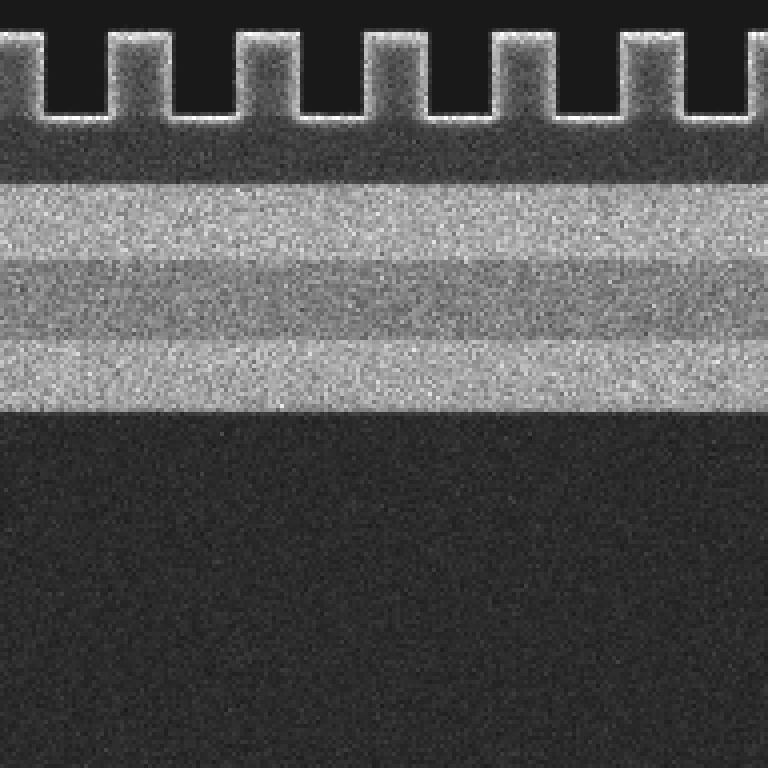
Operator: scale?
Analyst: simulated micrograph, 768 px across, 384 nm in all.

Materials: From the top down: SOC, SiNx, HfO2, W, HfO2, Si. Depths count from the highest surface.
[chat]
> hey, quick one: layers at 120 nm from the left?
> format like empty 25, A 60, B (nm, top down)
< SOC 42, SiNx 34, HfO2 38, W 40, HfO2 36, Si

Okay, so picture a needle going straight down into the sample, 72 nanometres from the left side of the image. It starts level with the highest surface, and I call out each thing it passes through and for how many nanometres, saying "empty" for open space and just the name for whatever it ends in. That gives SOC 42, SiNx 34, HfO2 38, W 40, HfO2 36, Si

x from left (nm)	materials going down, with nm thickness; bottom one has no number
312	SOC 42, SiNx 34, HfO2 38, W 40, HfO2 36, Si